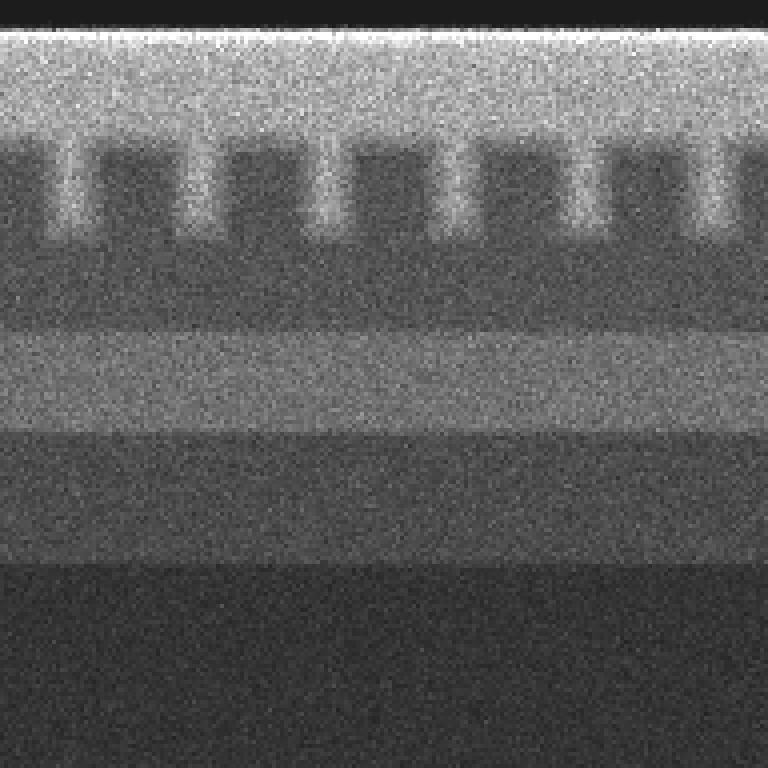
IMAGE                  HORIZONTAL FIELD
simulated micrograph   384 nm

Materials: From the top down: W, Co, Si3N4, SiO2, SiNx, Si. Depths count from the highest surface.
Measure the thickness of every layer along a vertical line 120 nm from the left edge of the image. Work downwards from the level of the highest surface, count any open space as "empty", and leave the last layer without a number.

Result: W 52, Co 8, Si3N4 90, SiO2 50, SiNx 66, Si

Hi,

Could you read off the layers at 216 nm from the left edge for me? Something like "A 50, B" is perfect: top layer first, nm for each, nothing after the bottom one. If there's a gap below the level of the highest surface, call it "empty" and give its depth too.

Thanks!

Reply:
W 52, Co 52, Si3N4 46, SiO2 50, SiNx 66, Si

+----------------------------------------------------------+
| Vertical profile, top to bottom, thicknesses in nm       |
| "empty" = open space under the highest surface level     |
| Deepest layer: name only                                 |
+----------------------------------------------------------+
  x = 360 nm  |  W 96, Co 8, Si3N4 46, SiO2 50, SiNx 66, Si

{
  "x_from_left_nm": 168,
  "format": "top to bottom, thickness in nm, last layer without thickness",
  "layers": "W 96, Co 8, Si3N4 46, SiO2 50, SiNx 66, Si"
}